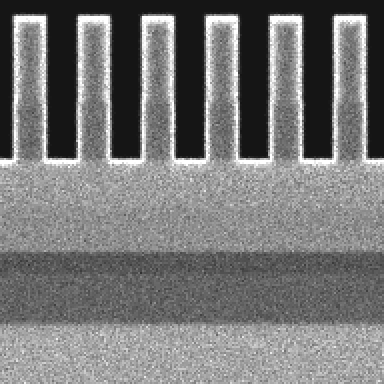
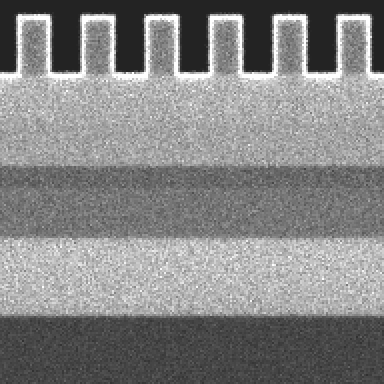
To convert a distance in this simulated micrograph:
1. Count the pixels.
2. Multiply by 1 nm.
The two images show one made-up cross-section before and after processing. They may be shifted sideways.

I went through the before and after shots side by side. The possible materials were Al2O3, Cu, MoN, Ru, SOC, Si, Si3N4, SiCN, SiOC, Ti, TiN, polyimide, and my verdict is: removed, SOC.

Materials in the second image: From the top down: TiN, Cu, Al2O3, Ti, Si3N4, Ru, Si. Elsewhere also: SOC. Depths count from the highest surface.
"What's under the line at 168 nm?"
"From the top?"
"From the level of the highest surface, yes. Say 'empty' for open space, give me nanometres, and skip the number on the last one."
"TiN 58, Cu 48, Al2O3 44, Ti 22, Si3N4 50, Ru 78, Si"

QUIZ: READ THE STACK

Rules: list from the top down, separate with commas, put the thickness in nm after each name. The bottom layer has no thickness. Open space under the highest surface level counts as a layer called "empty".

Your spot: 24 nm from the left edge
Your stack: TiN 58, Cu 48, Al2O3 44, Ti 22, Si3N4 50, Ru 78, Si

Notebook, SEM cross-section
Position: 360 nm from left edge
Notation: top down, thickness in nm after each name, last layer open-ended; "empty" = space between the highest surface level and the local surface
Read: TiN 58, Cu 48, Al2O3 44, Ti 22, Si3N4 50, Ru 78, Si